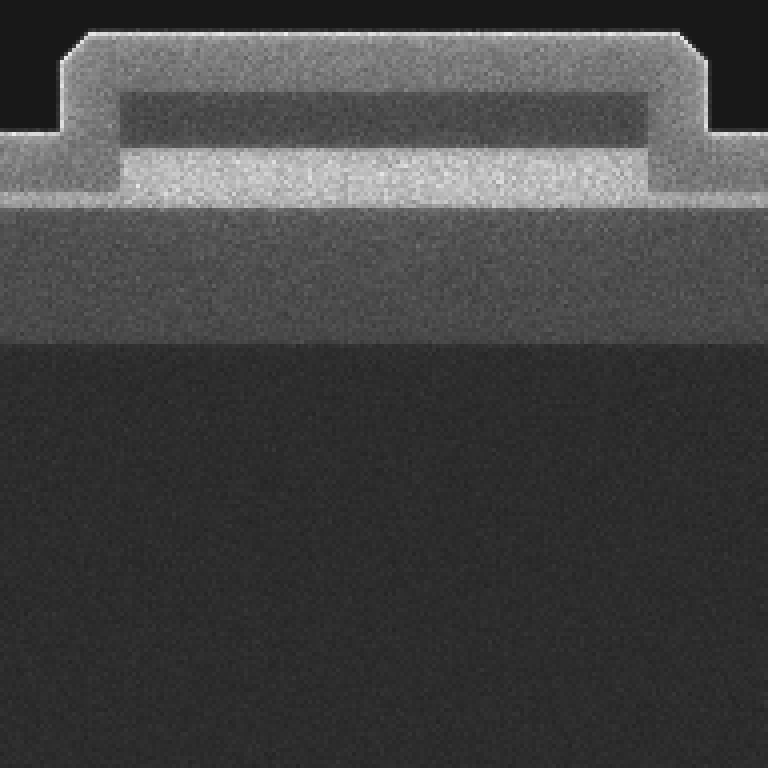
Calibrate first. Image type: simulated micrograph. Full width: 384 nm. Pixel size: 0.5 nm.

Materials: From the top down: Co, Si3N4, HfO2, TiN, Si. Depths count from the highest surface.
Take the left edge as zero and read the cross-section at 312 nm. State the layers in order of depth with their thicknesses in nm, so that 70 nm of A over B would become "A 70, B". Co 30, Si3N4 28, HfO2 30, TiN 68, Si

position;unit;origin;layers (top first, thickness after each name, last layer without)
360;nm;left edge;empty 50, Co 30, HfO2 8, TiN 68, Si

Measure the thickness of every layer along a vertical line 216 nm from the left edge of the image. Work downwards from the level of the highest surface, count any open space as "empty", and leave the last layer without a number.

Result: Co 30, Si3N4 28, HfO2 30, TiN 68, Si